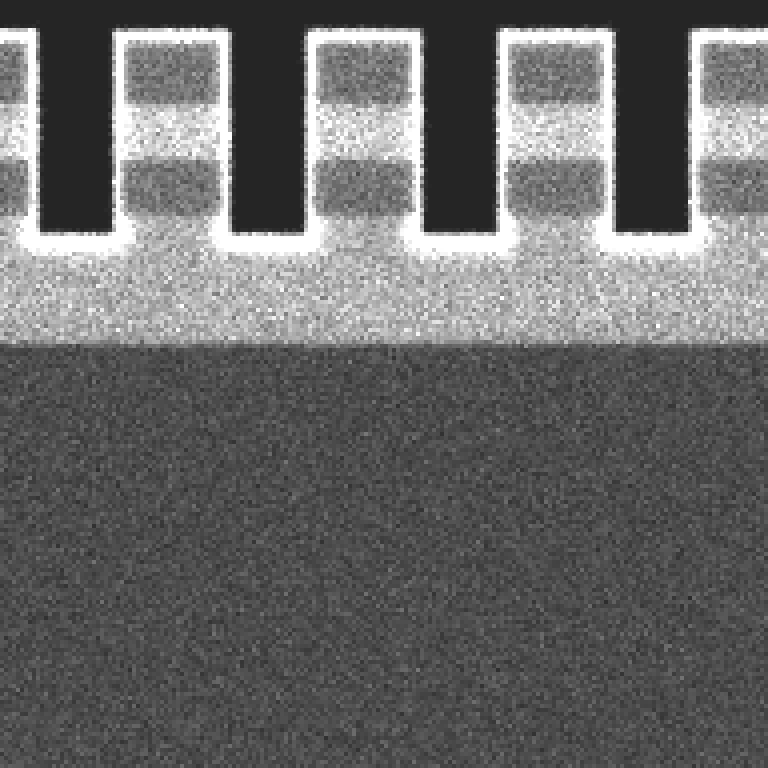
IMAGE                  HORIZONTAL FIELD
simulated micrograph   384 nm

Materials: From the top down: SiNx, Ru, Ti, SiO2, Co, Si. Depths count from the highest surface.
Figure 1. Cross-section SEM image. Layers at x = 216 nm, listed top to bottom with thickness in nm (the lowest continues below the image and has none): empty 102, SiO2 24, Co 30, Si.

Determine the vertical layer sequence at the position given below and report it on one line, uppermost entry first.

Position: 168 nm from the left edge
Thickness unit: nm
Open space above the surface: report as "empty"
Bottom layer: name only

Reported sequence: SiNx 36, Ru 28, Ti 28, SiO2 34, Co 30, Si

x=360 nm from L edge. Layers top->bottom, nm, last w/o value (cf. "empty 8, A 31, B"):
SiNx 36, Ru 28, Ti 28, SiO2 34, Co 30, Si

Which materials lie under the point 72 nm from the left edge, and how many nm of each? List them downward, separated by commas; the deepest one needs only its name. SiNx 36, Ru 28, Ti 28, SiO2 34, Co 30, Si